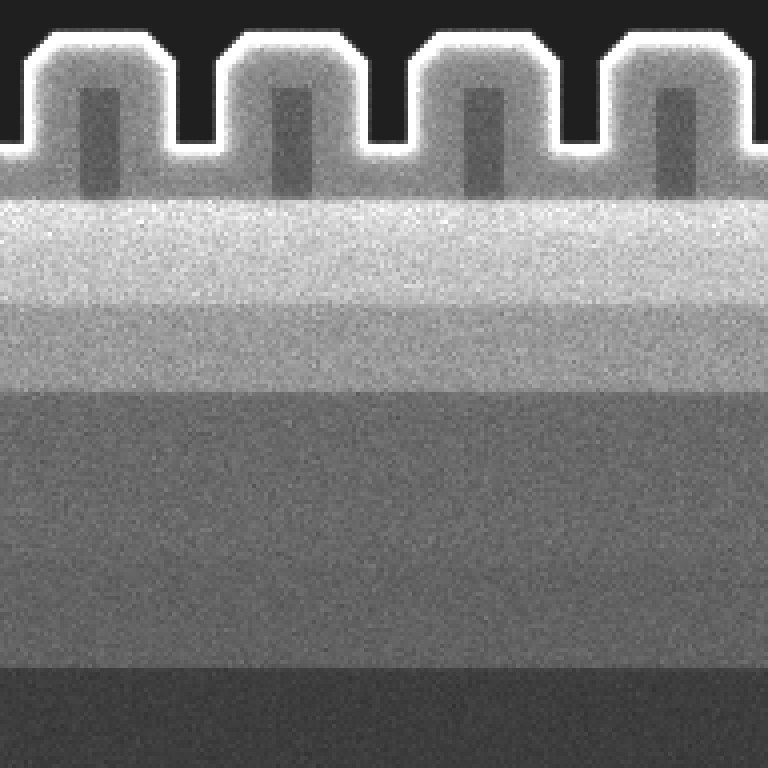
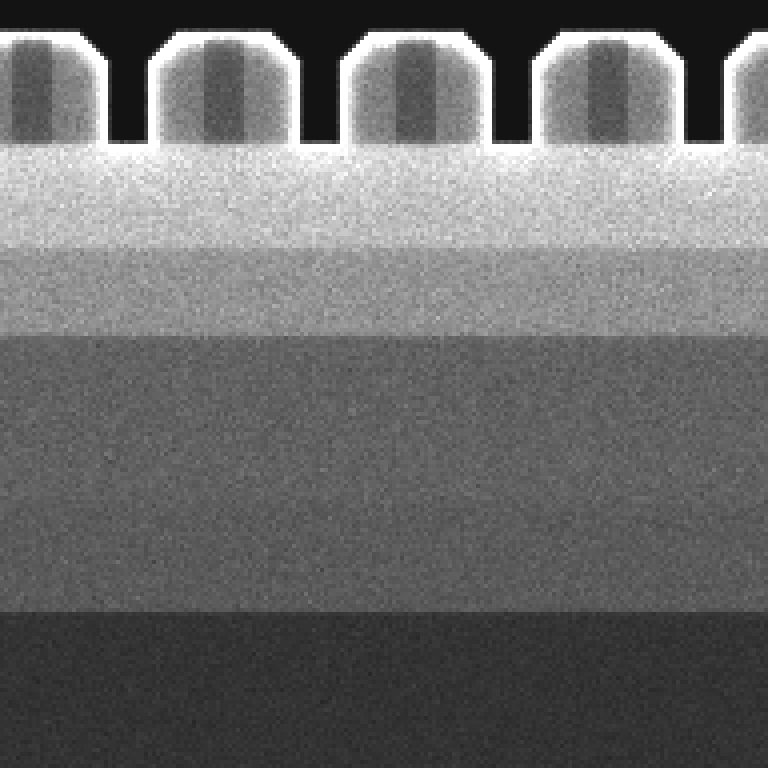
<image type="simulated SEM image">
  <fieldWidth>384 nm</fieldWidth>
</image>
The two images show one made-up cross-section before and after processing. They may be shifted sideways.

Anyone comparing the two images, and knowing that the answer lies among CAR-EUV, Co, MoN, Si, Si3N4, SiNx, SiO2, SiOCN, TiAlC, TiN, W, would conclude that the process removed SiO2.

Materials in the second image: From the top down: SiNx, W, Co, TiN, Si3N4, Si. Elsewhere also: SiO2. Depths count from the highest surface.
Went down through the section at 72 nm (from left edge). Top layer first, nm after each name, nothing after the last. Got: empty 56, W 52, Co 44, TiN 84, Si3N4 54, Si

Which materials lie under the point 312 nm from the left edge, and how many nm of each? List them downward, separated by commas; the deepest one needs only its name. SiNx 56, W 52, Co 44, TiN 84, Si3N4 54, Si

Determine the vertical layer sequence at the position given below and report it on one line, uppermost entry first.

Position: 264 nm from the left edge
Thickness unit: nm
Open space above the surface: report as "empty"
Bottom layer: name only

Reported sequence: empty 56, W 52, Co 44, TiN 84, Si3N4 54, Si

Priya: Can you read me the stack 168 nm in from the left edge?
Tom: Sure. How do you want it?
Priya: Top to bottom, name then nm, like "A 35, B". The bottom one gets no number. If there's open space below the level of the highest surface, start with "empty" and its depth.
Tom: empty 56, W 52, Co 44, TiN 84, Si3N4 54, Si